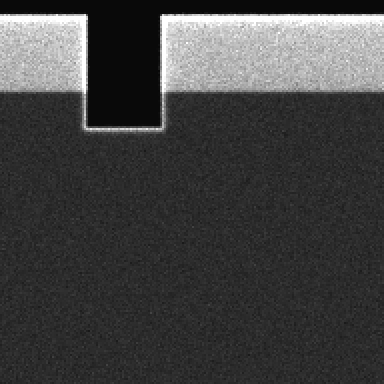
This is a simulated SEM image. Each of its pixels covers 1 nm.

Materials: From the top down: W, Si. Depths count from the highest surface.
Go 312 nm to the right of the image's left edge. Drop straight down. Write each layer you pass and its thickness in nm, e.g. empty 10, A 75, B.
W 76, Si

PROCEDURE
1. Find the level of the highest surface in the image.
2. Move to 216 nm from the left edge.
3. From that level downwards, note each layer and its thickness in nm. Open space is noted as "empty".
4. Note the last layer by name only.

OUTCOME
W 76, Si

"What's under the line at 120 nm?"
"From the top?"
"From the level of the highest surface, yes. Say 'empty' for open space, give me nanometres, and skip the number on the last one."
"empty 112, Si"